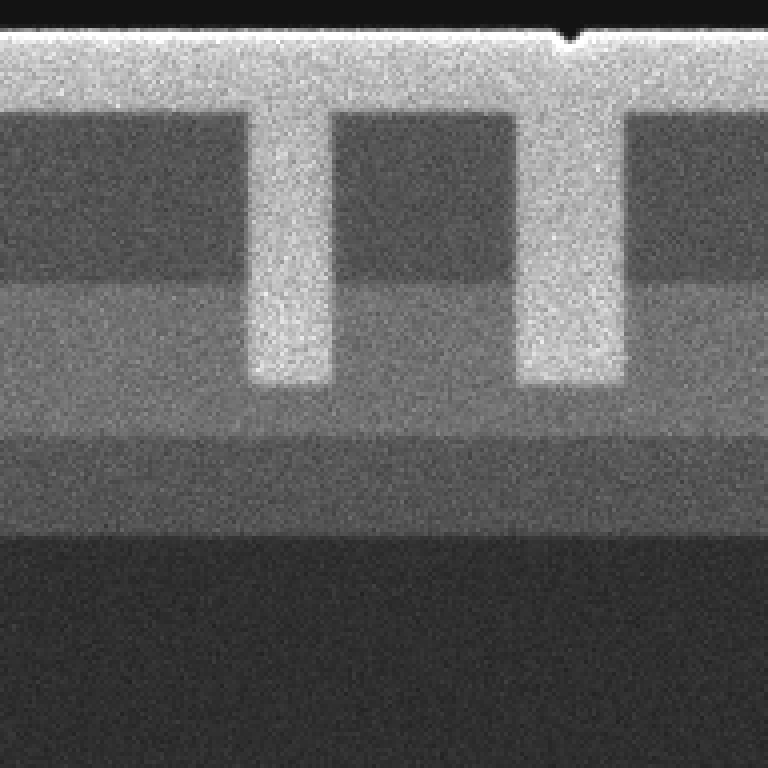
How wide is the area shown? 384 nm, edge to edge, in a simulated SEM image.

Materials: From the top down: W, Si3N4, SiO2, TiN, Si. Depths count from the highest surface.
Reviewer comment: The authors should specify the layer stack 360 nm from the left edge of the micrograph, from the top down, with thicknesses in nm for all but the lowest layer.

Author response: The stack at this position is W 40, Si3N4 86, SiO2 76, TiN 50, Si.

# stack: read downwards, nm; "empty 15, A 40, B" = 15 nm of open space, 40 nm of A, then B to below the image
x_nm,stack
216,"W 40, Si3N4 86, SiO2 76, TiN 50, Si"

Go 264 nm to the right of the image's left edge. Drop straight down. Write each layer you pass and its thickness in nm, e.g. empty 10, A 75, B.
W 176, SiO2 26, TiN 50, Si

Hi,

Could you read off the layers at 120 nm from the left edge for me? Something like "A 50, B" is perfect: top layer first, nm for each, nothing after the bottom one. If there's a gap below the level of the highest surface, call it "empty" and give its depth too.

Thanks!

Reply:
W 40, Si3N4 86, SiO2 76, TiN 50, Si